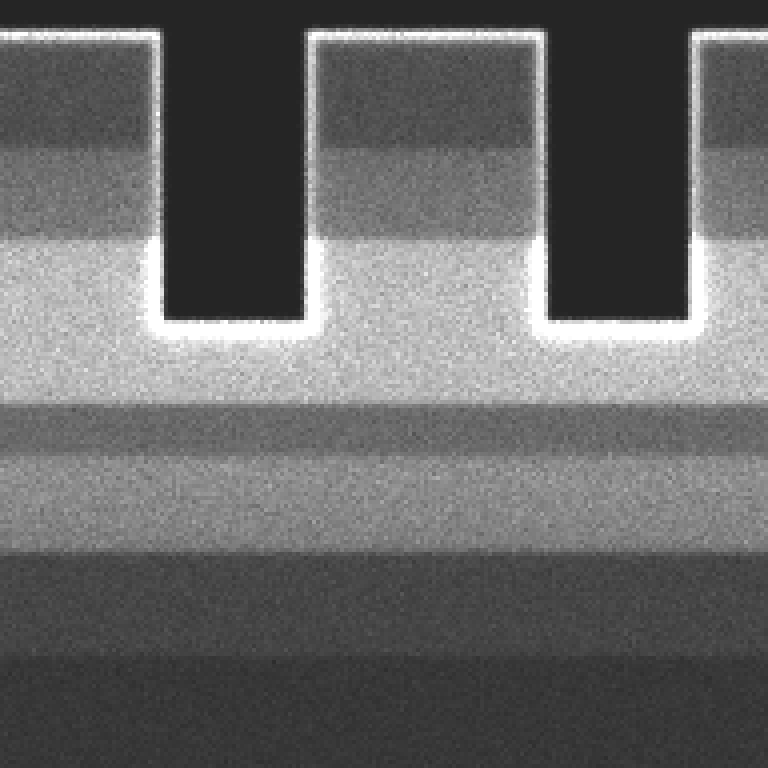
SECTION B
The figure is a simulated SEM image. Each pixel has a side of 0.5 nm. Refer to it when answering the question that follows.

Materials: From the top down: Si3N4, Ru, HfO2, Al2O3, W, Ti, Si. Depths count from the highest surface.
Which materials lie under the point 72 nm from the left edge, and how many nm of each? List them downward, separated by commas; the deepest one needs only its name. Si3N4 58, Ru 46, HfO2 82, Al2O3 26, W 48, Ti 52, Si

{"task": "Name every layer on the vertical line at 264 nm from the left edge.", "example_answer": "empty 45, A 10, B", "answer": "Si3N4 58, Ru 46, HfO2 82, Al2O3 26, W 48, Ti 52, Si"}